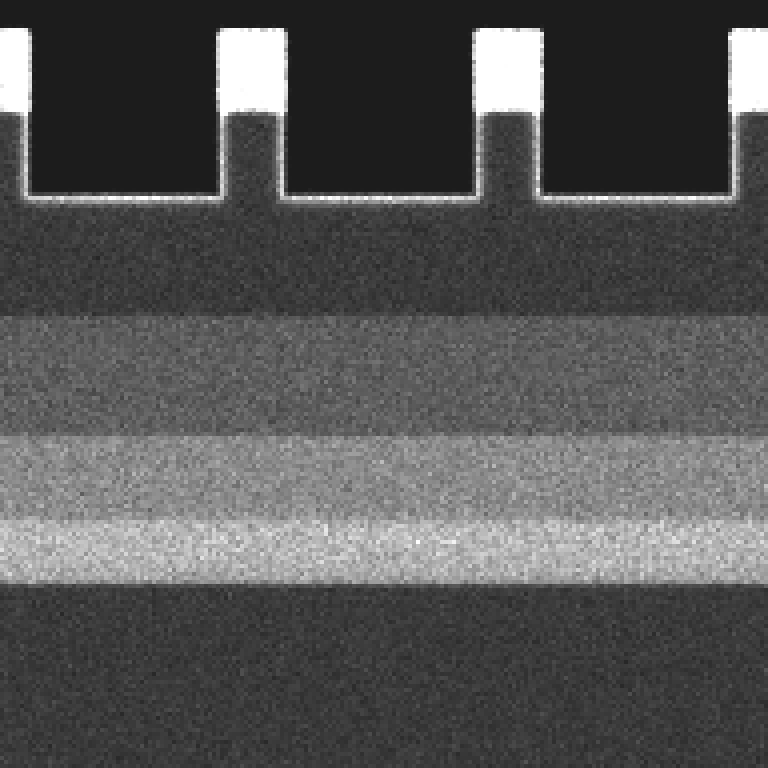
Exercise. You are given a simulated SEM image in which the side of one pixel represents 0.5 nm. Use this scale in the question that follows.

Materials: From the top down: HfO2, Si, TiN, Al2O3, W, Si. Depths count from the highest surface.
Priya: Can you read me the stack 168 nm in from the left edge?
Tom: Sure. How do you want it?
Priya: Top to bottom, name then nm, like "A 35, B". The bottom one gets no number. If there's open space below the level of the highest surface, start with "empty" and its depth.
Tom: empty 82, Si 60, TiN 60, Al2O3 42, W 32, Si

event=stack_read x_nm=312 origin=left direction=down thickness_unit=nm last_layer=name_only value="empty 82, Si 60, TiN 60, Al2O3 42, W 32, Si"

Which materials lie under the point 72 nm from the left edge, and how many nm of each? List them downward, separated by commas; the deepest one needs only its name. empty 82, Si 60, TiN 60, Al2O3 42, W 32, Si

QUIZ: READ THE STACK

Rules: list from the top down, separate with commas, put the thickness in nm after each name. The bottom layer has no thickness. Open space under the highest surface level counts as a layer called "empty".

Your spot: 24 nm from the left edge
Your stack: empty 82, Si 60, TiN 60, Al2O3 42, W 32, Si